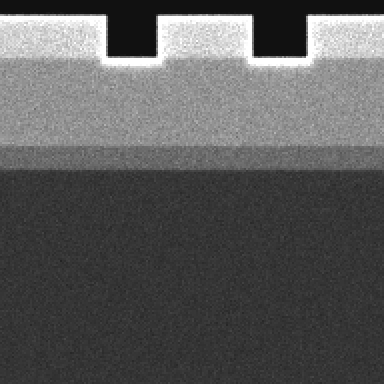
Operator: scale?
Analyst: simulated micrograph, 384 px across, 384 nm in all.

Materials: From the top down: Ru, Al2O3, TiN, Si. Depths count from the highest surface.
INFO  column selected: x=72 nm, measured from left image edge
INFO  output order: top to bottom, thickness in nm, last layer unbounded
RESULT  Ru 42, Al2O3 88, TiN 24, Si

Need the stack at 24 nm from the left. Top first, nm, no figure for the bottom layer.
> Ru 42, Al2O3 88, TiN 24, Si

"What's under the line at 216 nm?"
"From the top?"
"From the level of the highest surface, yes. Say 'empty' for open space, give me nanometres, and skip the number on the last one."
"Ru 42, Al2O3 88, TiN 24, Si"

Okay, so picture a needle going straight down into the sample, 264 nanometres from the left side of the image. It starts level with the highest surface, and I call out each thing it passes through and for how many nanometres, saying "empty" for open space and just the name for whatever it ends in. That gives empty 42, Al2O3 88, TiN 24, Si